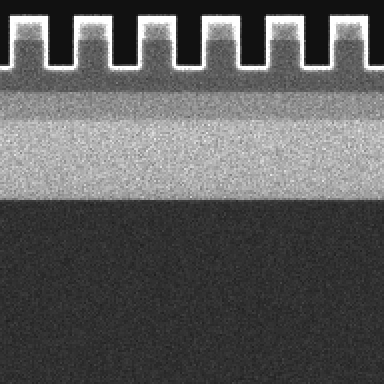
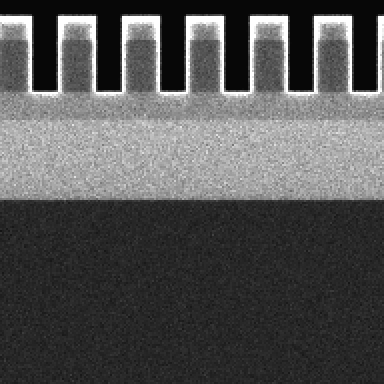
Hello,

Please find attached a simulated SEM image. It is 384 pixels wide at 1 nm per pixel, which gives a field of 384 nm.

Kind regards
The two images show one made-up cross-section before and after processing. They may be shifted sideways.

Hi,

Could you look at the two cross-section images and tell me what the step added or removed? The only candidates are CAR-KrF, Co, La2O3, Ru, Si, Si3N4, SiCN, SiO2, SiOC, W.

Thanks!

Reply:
removed Si3N4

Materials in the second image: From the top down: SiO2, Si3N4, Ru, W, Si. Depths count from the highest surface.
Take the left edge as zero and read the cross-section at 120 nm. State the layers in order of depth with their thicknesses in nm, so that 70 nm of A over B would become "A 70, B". empty 76, Ru 28, W 80, Si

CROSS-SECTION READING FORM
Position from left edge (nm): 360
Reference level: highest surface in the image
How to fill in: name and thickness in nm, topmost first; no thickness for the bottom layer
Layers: empty 76, Ru 28, W 80, Si